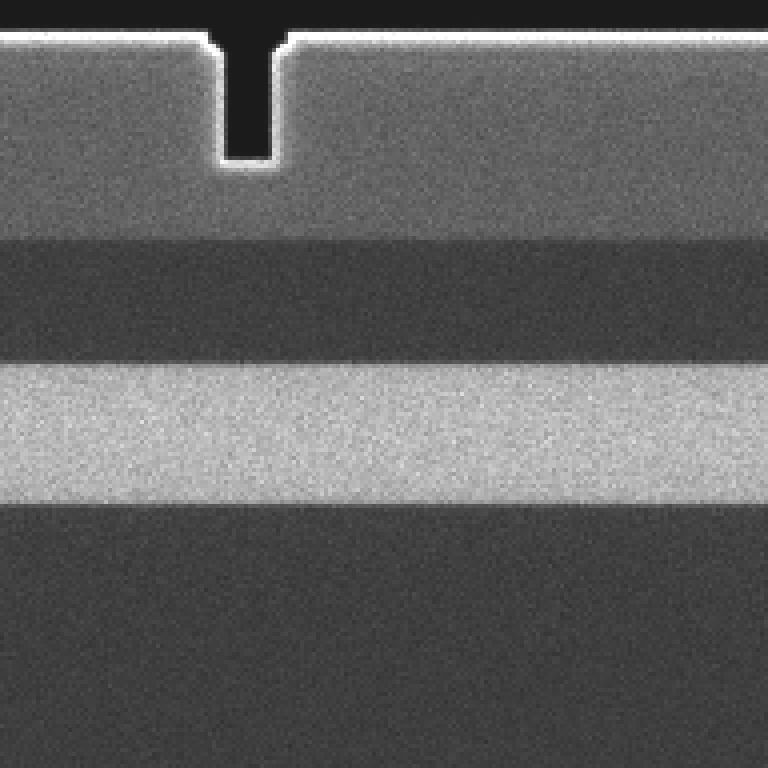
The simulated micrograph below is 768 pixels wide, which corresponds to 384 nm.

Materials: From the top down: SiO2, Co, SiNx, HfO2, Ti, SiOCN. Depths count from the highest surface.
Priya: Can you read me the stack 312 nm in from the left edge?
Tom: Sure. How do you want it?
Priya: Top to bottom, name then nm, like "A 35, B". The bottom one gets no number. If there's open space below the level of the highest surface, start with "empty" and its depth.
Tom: SiO2 14, Co 90, SiNx 62, HfO2 70, Ti 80, SiOCN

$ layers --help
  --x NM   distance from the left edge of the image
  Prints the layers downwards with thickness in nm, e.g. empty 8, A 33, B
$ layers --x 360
SiO2 14, Co 90, SiNx 62, HfO2 70, Ti 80, SiOCN